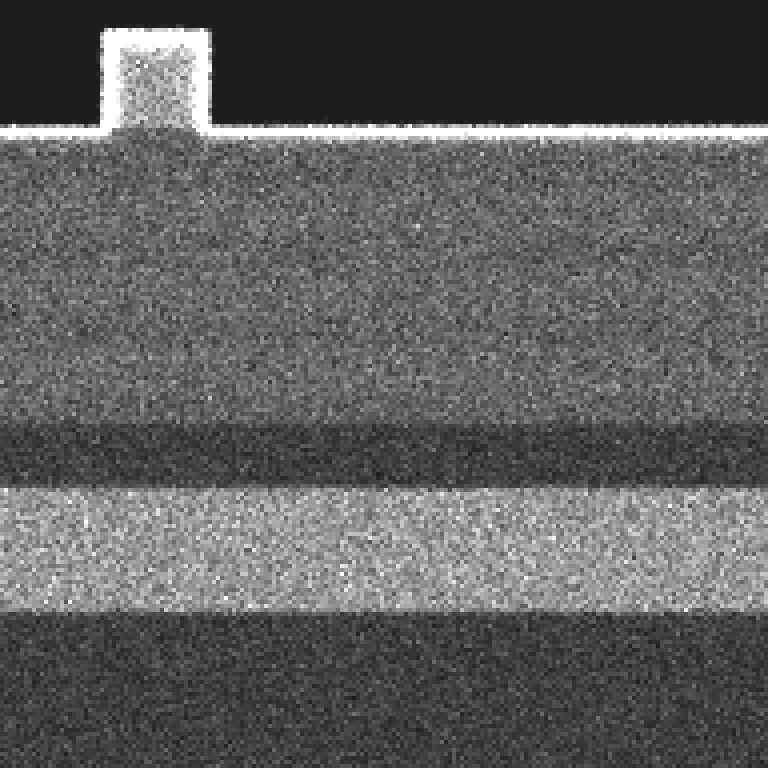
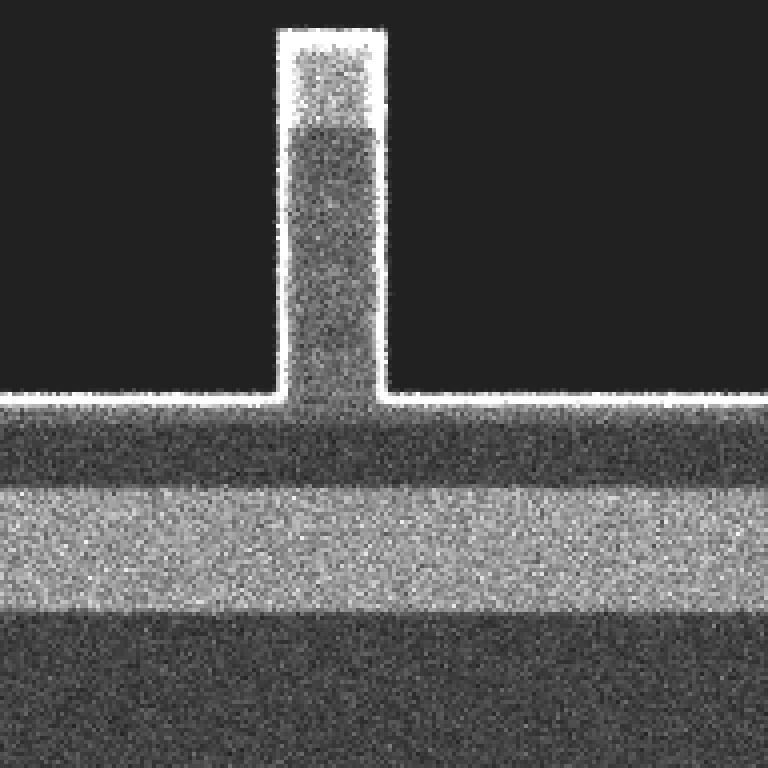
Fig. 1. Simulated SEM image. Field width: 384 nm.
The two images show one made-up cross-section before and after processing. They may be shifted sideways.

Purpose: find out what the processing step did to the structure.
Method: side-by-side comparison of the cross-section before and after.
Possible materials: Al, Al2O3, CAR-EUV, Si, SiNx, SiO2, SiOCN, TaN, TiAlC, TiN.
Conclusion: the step removed SiOCN and TiN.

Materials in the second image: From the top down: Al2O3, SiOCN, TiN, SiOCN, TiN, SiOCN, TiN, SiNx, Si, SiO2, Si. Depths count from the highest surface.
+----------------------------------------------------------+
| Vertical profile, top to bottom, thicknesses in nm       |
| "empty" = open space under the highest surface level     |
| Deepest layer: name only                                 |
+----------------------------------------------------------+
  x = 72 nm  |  empty 182, SiNx 14, Si 32, SiO2 62, Si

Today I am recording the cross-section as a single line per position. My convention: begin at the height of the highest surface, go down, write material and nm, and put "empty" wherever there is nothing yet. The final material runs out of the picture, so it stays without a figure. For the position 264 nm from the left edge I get empty 182, SiNx 14, Si 32, SiO2 62, Si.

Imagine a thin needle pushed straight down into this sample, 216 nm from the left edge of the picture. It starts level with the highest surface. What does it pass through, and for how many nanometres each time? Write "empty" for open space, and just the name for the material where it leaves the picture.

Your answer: empty 182, SiNx 14, Si 32, SiO2 62, Si